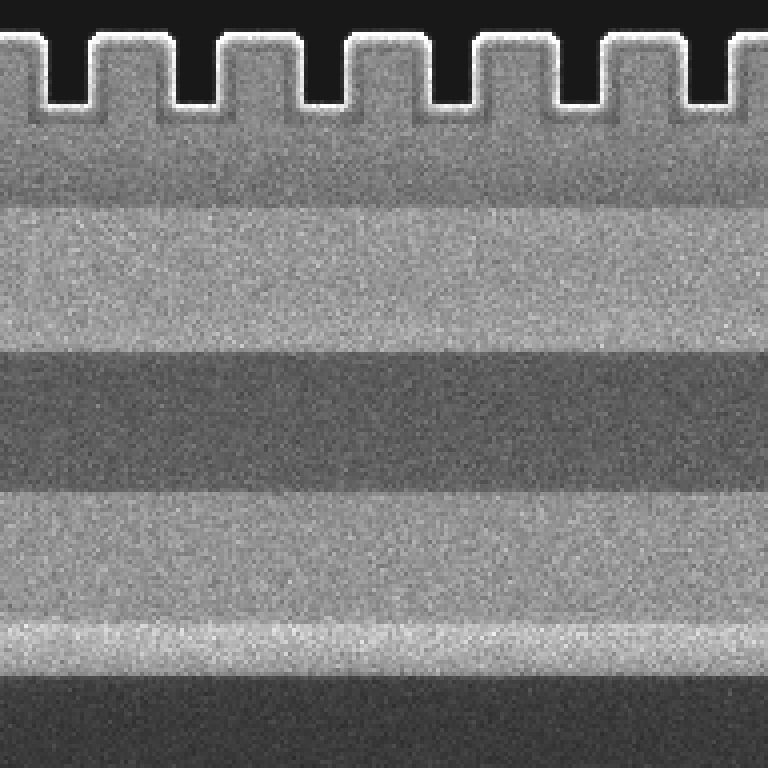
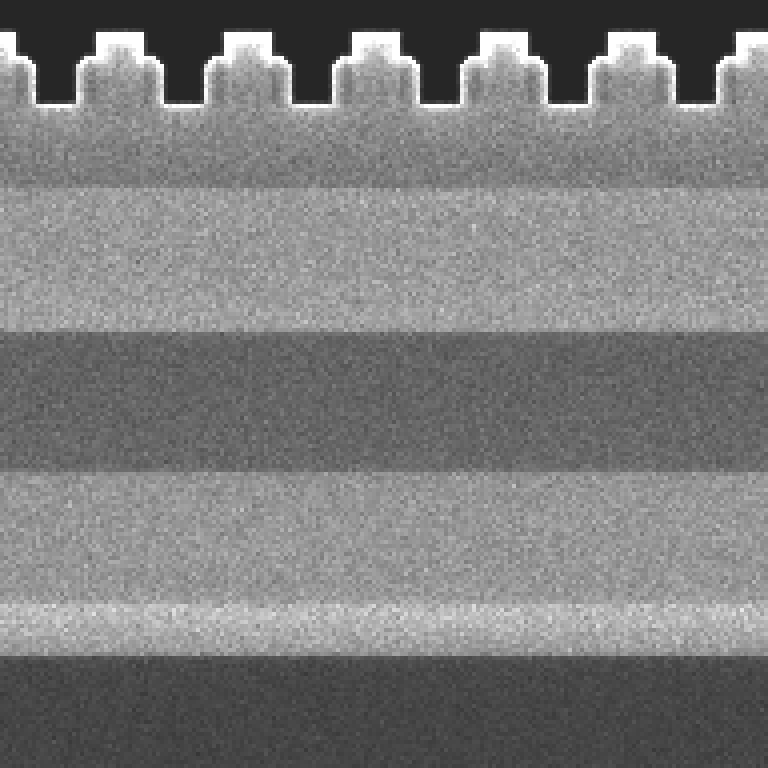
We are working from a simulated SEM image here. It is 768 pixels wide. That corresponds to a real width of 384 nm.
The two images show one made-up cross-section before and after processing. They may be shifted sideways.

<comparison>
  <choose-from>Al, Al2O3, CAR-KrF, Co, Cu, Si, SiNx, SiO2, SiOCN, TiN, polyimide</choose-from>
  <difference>SiOCN removed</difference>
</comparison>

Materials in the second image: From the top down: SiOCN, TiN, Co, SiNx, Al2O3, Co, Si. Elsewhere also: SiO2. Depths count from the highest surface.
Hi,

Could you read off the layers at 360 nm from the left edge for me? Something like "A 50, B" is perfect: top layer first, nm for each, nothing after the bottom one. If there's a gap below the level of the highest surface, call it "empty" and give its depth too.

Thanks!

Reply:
empty 14, SiOCN 22, TiN 42, Co 72, SiNx 70, Al2O3 66, Co 26, Si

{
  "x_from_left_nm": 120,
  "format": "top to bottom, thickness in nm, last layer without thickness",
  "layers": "SiO2 36, TiN 42, Co 72, SiNx 70, Al2O3 66, Co 26, Si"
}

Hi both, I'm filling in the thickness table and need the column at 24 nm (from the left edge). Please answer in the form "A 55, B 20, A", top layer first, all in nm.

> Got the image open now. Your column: empty 36, TiN 42, Co 72, SiNx 70, Al2O3 66, Co 26, Si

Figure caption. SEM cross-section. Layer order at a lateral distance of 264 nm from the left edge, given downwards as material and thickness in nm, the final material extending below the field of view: empty 12, SiOCN 24, TiN 42, Co 72, SiNx 70, Al2O3 66, Co 26, Si